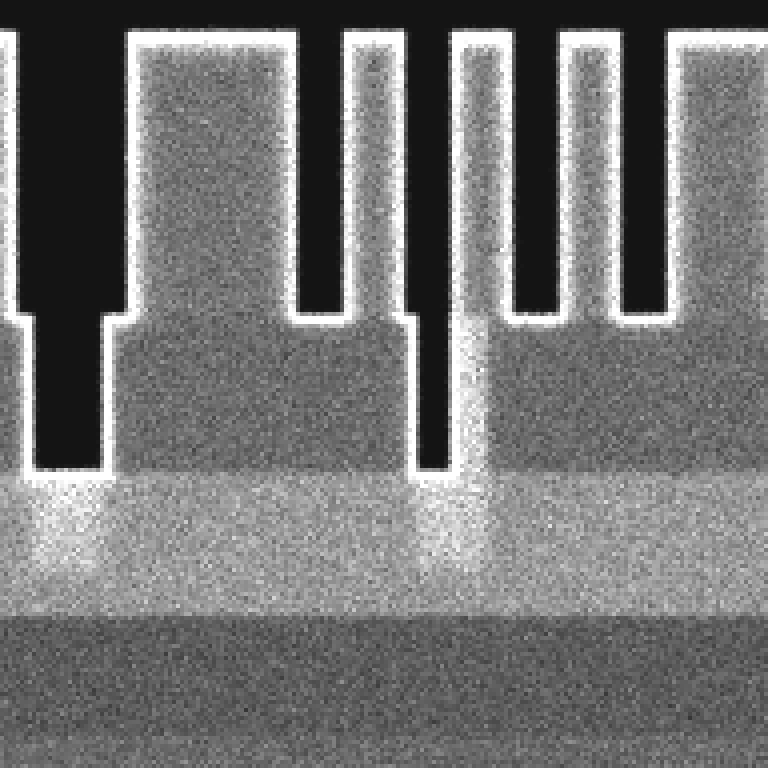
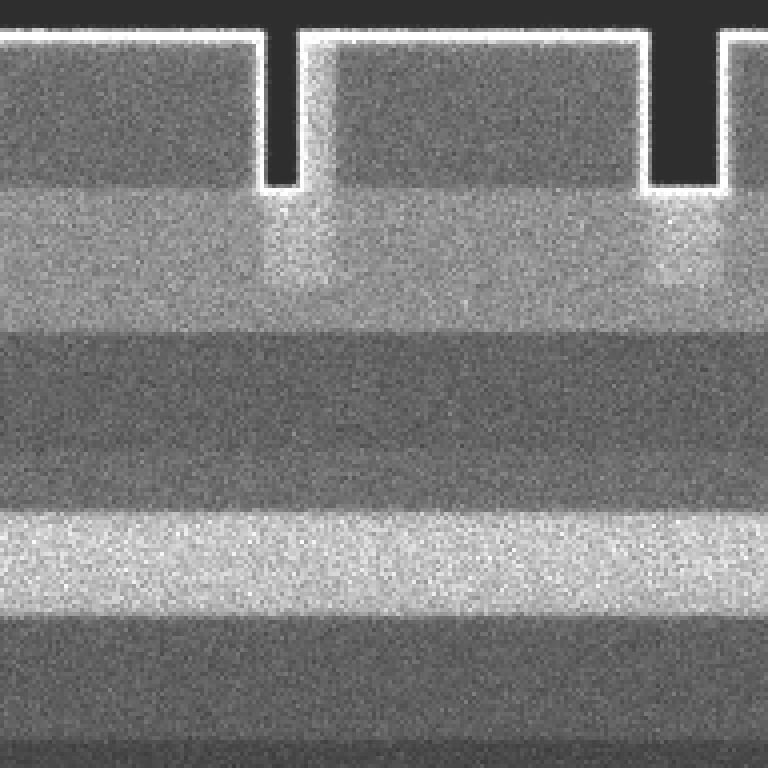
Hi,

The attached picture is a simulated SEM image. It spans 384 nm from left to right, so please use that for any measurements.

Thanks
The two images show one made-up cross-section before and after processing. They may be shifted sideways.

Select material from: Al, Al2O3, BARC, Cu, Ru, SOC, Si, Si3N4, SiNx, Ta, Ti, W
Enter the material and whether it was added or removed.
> SOC / removed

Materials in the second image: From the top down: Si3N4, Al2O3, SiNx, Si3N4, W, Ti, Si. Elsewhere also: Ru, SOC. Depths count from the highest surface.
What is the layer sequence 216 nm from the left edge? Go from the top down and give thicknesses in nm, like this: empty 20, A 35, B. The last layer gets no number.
Si3N4 78, Al2O3 72, SiNx 60, Si3N4 30, W 52, Ti 62, Si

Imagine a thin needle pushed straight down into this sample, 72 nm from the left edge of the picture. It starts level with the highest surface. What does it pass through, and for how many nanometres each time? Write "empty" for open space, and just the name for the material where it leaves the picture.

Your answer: Si3N4 78, Al2O3 72, SiNx 60, Si3N4 30, W 52, Ti 62, Si